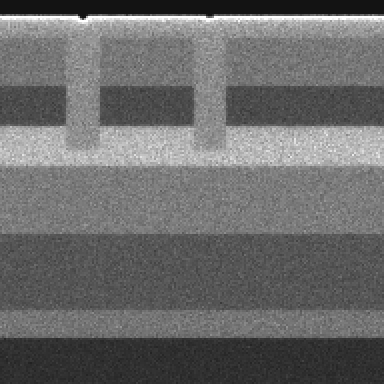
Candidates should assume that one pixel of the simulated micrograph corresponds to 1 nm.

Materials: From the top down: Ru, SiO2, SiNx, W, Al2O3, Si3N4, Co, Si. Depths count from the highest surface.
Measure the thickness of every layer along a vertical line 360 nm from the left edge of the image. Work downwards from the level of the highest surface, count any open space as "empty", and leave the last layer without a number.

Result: Ru 22, SiO2 48, SiNx 40, W 40, Al2O3 68, Si3N4 76, Co 28, Si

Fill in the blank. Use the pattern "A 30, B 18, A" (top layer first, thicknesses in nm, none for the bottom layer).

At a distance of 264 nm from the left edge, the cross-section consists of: Ru 22, SiO2 48, SiNx 40, W 40, Al2O3 68, Si3N4 76, Co 28, Si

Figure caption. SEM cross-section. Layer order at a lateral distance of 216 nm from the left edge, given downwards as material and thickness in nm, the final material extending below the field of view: Ru 134, W 16, Al2O3 68, Si3N4 76, Co 28, Si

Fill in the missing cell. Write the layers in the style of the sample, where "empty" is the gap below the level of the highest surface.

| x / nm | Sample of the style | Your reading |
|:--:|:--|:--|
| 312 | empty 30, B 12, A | Ru 22, SiO2 48, SiNx 40, W 40, Al2O3 68, Si3N4 76, Co 28, Si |